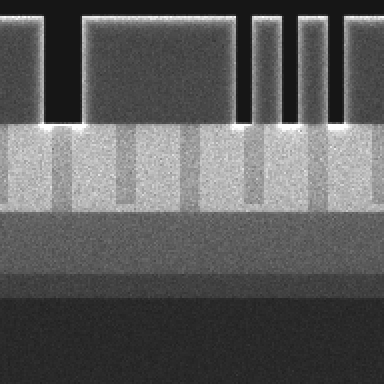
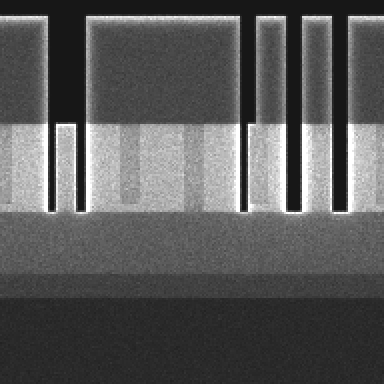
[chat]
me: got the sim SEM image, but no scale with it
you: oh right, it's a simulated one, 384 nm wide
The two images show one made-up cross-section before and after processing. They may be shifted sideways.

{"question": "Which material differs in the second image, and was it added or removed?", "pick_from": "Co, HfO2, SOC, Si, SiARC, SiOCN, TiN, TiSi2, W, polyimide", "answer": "HfO2, removed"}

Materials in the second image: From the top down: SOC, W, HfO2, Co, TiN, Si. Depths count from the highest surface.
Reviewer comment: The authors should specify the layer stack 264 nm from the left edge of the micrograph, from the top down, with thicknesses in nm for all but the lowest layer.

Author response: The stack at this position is SOC 108, W 80, HfO2 8, Co 62, TiN 24, Si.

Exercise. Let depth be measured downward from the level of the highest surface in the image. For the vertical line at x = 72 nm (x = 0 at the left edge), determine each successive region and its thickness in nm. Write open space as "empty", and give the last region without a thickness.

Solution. empty 108, W 88, Co 62, TiN 24, Si